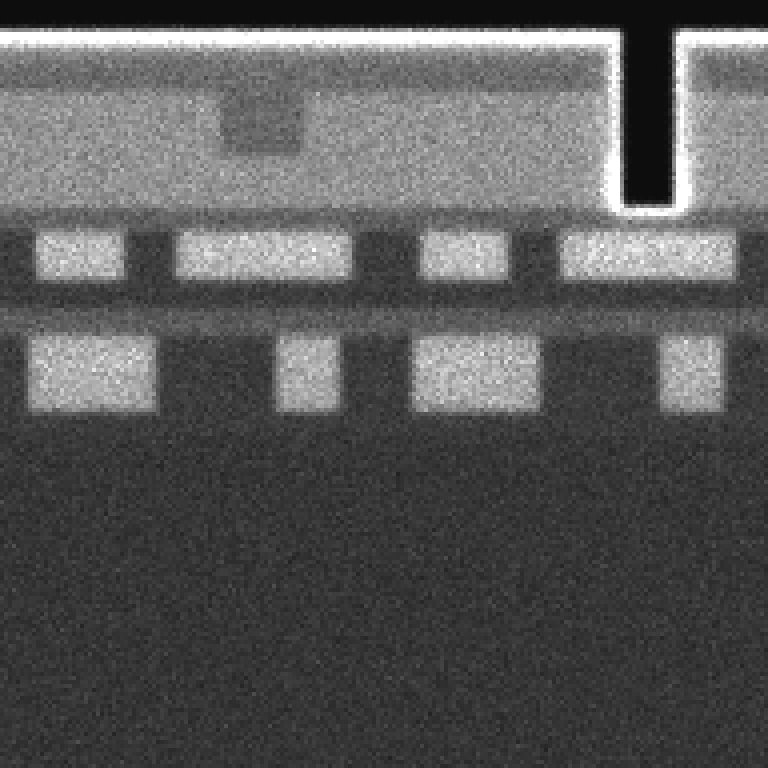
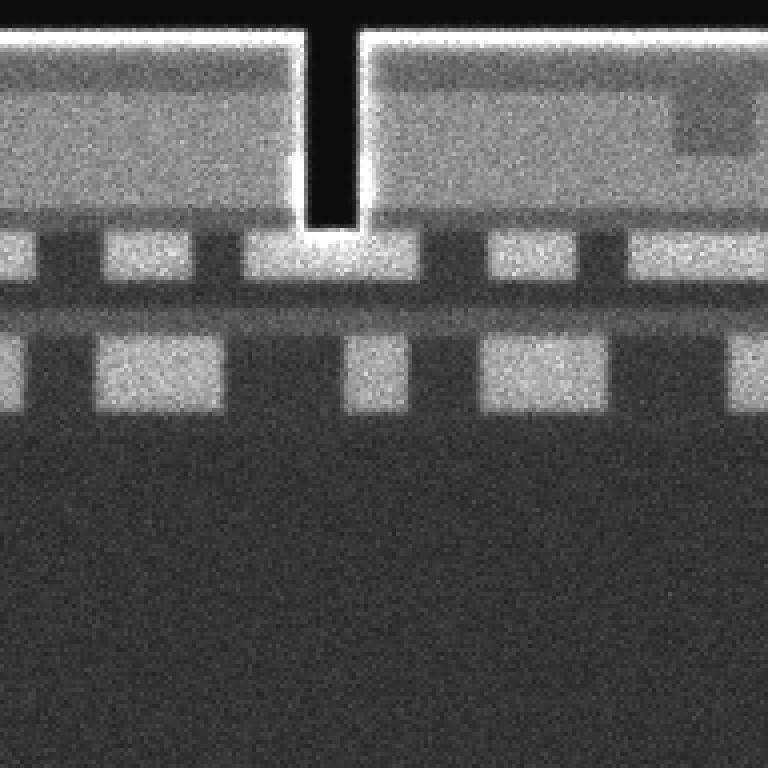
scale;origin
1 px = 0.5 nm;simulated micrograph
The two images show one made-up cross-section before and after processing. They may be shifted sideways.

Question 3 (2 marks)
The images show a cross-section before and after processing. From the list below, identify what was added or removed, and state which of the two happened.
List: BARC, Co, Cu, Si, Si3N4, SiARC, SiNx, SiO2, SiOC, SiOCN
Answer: SiNx was removed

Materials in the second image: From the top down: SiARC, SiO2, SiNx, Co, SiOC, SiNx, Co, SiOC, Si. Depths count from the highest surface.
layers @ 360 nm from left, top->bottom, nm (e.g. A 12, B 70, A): SiARC 62, SiO2 26, SiNx 12, Co 24, SiOC 14, SiNx 14, SiOC 50, Si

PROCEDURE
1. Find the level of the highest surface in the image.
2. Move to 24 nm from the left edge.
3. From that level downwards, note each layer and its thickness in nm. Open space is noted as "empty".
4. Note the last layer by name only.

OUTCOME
SiARC 30, SiO2 58, SiNx 12, SiOC 38, SiNx 14, SiOC 50, Si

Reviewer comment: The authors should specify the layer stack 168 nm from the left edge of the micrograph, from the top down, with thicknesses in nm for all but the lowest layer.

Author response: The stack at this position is empty 100, Co 24, SiOC 14, SiNx 14, SiOC 50, Si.